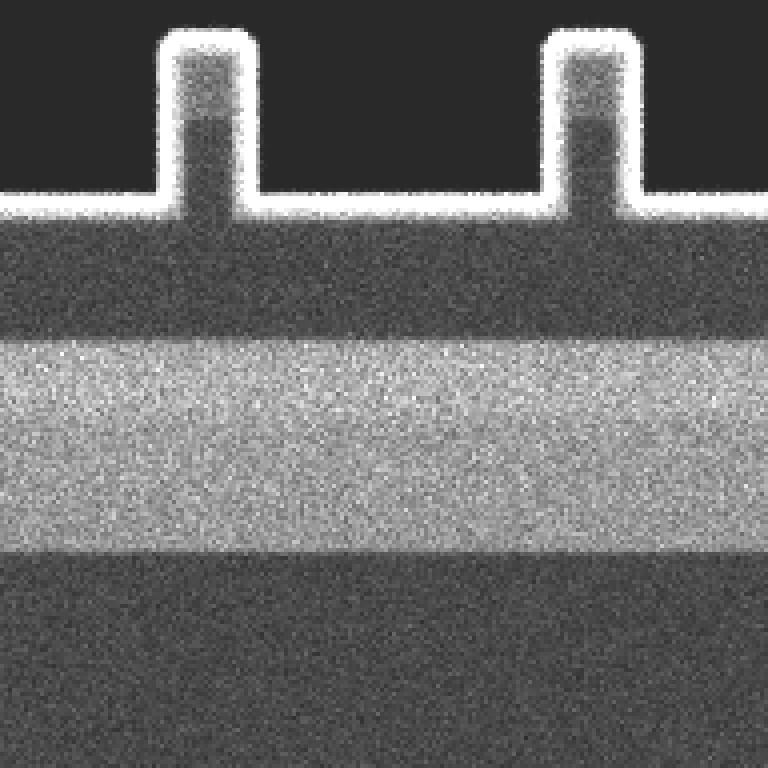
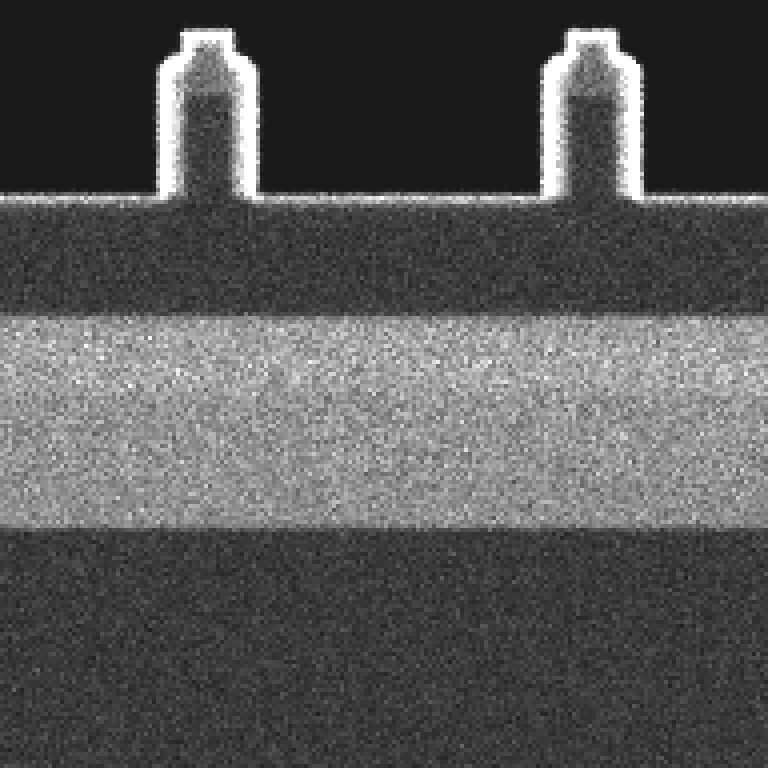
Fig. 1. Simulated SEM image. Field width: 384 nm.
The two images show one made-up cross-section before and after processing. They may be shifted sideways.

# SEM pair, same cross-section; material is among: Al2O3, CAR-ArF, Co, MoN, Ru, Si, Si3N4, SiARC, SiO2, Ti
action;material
removed;Al2O3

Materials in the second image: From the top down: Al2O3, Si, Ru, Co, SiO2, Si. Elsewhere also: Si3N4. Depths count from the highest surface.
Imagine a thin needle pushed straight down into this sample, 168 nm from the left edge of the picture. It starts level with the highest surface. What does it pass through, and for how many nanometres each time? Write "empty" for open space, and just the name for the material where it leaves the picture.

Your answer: empty 82, Si 60, Ru 38, Co 42, SiO2 26, Si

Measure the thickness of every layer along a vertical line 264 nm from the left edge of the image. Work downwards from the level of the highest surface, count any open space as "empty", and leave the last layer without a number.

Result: empty 82, Si 60, Ru 38, Co 42, SiO2 26, Si